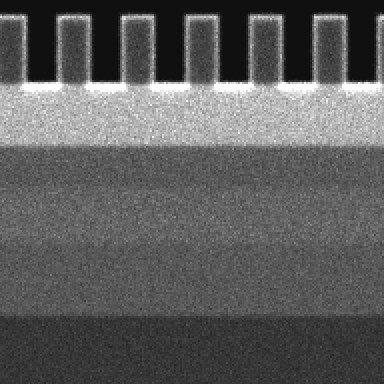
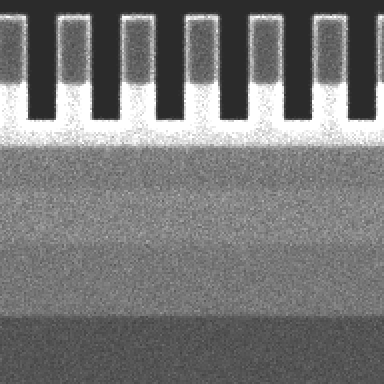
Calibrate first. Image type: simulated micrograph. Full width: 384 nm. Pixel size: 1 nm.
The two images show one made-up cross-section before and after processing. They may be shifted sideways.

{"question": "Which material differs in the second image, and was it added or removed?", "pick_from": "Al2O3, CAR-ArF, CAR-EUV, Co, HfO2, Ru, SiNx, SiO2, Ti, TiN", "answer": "HfO2, removed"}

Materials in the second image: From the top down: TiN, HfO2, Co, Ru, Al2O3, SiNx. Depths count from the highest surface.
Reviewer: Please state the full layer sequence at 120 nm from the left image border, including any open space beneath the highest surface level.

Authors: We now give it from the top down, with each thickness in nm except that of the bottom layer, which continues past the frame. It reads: empty 106, HfO2 24, Co 42, Ru 56, Al2O3 72, SiNx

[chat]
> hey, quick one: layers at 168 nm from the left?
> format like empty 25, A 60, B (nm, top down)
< empty 106, HfO2 24, Co 42, Ru 56, Al2O3 72, SiNx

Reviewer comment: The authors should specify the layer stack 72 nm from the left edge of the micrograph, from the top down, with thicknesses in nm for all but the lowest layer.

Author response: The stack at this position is TiN 68, HfO2 62, Co 42, Ru 56, Al2O3 72, SiNx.